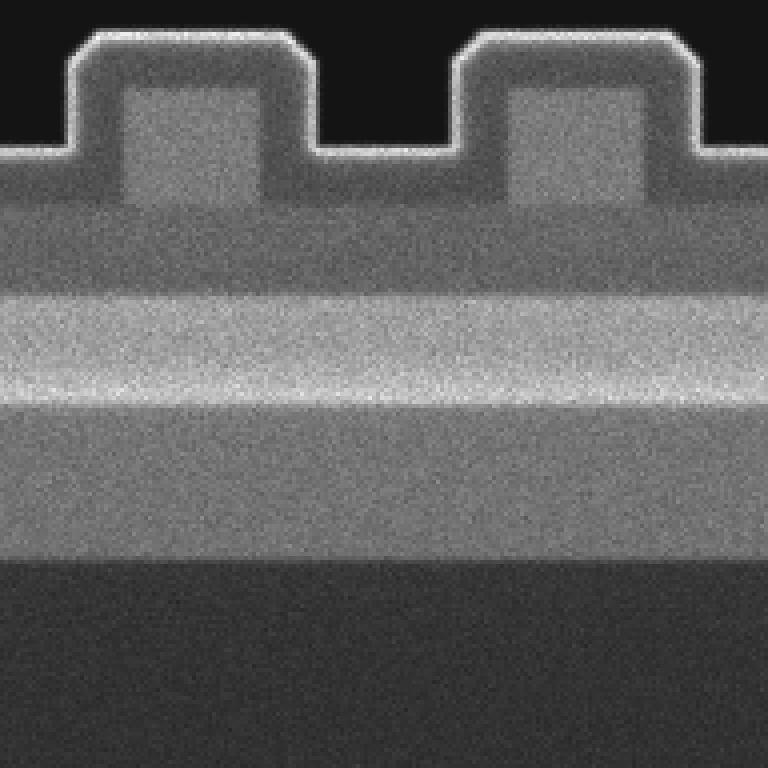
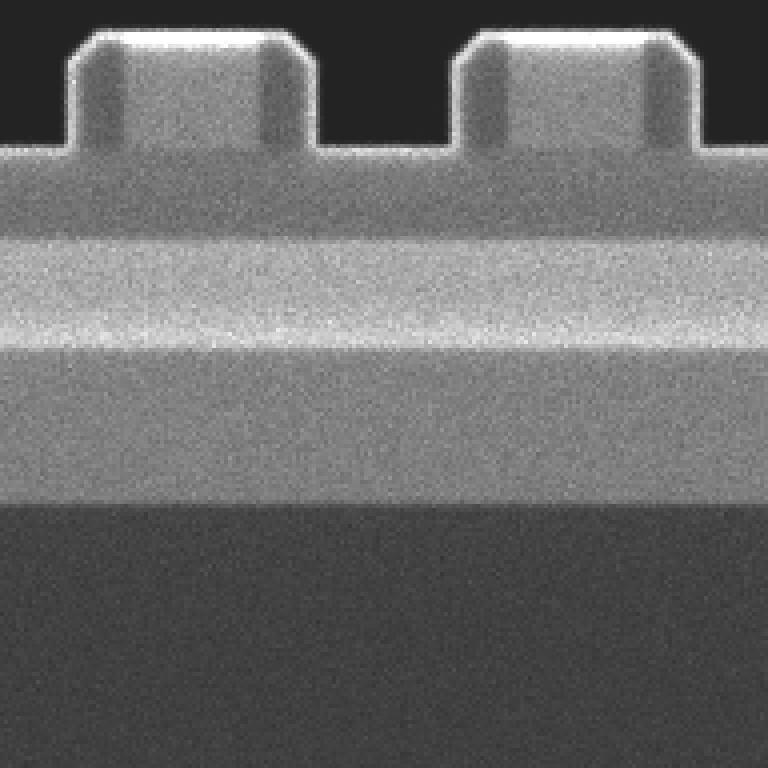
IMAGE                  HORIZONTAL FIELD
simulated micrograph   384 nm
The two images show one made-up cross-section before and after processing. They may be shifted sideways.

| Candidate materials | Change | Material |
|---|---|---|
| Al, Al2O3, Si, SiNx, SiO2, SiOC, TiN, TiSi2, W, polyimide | removed | SiNx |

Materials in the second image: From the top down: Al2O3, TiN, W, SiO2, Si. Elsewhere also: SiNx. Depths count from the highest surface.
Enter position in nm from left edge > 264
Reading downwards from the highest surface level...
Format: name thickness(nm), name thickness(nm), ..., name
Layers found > Al2O3 58, TiN 46, W 54, SiO2 78, Si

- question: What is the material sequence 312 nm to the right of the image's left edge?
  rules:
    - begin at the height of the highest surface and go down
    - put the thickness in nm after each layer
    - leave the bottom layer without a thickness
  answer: Al2O3 58, TiN 46, W 54, SiO2 78, Si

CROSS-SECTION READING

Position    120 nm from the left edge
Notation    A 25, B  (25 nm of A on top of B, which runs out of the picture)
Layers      Al2O3 58, TiN 46, W 54, SiO2 78, Si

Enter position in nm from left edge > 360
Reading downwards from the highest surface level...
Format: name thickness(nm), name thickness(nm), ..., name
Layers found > empty 58, TiN 46, W 54, SiO2 78, Si